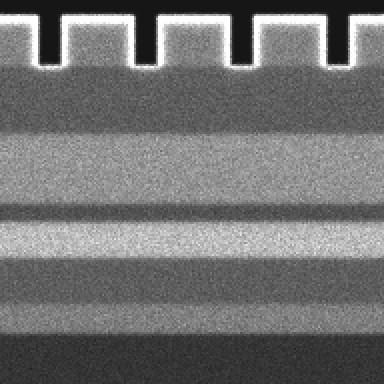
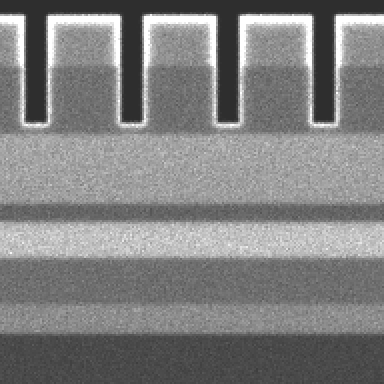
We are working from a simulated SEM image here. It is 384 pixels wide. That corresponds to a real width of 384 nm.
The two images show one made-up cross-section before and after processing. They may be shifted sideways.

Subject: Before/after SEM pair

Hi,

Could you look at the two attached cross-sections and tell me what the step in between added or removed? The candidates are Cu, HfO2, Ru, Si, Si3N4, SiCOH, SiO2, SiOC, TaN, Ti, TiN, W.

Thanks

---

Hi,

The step removed TiN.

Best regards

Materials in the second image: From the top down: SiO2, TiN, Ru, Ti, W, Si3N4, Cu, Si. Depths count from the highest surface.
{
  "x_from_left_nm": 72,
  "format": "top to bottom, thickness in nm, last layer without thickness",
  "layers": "SiO2 50, TiN 68, Ru 70, Ti 18, W 36, Si3N4 46, Cu 30, Si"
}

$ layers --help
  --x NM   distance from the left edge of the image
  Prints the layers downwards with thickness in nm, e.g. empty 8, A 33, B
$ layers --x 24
empty 108, TiN 10, Ru 70, Ti 18, W 36, Si3N4 46, Cu 30, Si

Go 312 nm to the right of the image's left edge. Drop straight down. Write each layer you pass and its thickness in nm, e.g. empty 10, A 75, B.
empty 108, TiN 10, Ru 70, Ti 18, W 36, Si3N4 46, Cu 30, Si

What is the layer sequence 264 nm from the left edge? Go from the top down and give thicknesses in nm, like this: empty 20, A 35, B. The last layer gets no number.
SiO2 50, TiN 68, Ru 70, Ti 18, W 36, Si3N4 46, Cu 30, Si